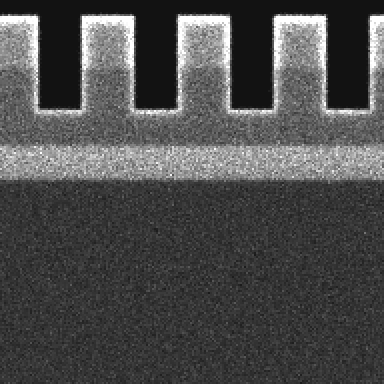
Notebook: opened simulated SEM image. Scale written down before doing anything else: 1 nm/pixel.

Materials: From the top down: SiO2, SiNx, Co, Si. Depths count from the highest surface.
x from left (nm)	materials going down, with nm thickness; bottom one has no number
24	SiO2 52, SiNx 78, Co 34, Si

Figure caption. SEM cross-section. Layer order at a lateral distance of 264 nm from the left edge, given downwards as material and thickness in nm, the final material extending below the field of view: empty 94, SiNx 36, Co 34, Si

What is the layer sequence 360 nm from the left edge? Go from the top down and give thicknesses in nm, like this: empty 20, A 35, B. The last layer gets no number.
empty 94, SiNx 36, Co 34, Si